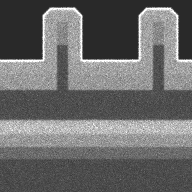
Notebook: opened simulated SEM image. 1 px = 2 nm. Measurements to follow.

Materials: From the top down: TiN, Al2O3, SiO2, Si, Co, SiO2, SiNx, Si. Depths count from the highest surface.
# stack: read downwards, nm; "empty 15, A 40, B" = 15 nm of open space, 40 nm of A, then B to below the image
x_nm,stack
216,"empty 104, TiN 8, Al2O3 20, SiO2 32, Si 60, Co 28, SiO2 26, SiNx 24, Si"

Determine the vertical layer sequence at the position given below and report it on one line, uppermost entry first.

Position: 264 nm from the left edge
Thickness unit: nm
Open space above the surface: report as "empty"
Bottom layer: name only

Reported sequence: empty 104, TiN 8, Al2O3 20, SiO2 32, Si 60, Co 28, SiO2 26, SiNx 24, Si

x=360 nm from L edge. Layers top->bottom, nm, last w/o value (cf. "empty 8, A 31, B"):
empty 104, TiN 8, Al2O3 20, SiO2 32, Si 60, Co 28, SiO2 26, SiNx 24, Si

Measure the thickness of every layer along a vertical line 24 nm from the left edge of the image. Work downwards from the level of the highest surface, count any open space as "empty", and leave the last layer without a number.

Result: empty 104, TiN 8, Al2O3 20, SiO2 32, Si 60, Co 28, SiO2 26, SiNx 24, Si